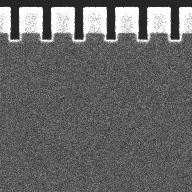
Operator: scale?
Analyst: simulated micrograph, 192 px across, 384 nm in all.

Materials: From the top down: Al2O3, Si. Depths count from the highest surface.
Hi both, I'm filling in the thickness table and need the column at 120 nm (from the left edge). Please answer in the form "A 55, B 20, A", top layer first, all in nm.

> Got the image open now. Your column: Al2O3 50, Si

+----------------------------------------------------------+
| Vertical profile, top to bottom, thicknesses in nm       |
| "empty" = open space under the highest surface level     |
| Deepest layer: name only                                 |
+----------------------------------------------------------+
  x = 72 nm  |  Al2O3 50, Si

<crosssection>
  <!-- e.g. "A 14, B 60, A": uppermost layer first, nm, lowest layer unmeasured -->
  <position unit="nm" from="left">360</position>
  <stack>Al2O3 50, Si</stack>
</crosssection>